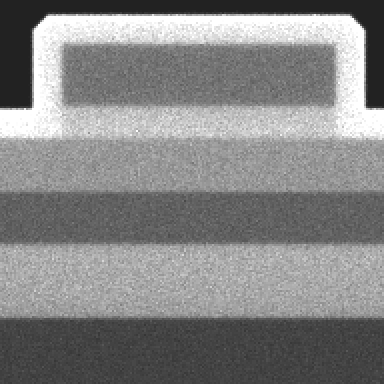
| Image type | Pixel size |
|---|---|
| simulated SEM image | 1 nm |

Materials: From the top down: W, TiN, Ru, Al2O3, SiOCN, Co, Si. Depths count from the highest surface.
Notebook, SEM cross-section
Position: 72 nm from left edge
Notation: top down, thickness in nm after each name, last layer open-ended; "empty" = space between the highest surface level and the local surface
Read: W 28, TiN 62, Ru 32, Al2O3 54, SiOCN 52, Co 74, Si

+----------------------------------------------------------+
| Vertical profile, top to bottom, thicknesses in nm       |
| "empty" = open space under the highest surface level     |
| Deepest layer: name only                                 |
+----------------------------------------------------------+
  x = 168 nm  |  W 28, TiN 62, Ru 32, Al2O3 54, SiOCN 52, Co 74, Si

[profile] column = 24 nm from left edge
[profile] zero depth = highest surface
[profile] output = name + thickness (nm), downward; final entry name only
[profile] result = empty 94, W 28, Al2O3 54, SiOCN 52, Co 74, Si